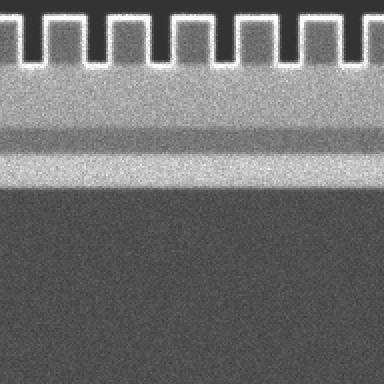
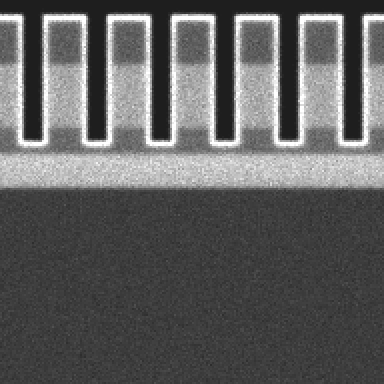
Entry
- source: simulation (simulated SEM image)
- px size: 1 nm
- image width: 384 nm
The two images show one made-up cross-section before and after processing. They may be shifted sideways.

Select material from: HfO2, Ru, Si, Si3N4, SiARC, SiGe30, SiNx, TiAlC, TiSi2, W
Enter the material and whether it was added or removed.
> Ru and Si3N4 / removed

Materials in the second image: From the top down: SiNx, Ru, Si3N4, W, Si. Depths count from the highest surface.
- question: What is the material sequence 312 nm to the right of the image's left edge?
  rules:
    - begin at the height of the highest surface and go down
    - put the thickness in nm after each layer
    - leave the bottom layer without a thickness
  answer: SiNx 48, Ru 64, Si3N4 26, W 34, Si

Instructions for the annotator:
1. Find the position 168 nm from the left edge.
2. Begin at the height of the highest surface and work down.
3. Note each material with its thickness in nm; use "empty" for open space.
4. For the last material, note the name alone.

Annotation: empty 126, Si3N4 12, W 34, Si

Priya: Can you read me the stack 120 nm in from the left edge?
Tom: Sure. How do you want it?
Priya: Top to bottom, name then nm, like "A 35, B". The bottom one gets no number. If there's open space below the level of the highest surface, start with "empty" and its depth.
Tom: SiNx 48, Ru 64, Si3N4 26, W 34, Si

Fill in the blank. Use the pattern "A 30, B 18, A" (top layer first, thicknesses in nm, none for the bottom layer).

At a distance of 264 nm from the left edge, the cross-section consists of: SiNx 48, Ru 64, Si3N4 26, W 34, Si